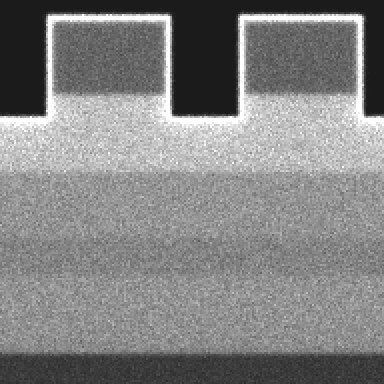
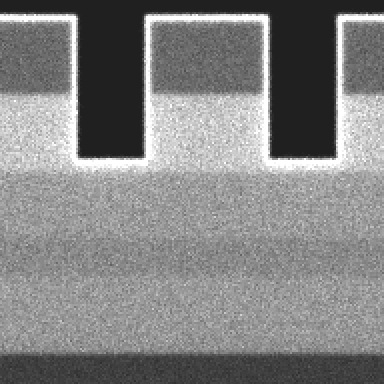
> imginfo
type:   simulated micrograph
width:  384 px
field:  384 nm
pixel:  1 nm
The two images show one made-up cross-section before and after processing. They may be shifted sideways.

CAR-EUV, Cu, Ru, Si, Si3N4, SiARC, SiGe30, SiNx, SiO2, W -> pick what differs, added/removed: W removed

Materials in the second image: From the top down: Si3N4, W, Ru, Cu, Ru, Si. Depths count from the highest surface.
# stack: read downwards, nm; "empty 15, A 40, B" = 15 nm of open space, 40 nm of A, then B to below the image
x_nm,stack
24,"Si3N4 78, W 78, Ru 66, Cu 38, Ru 78, Si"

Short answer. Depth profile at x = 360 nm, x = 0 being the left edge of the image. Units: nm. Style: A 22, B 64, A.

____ Si3N4 78, W 78, Ru 66, Cu 38, Ru 78, Si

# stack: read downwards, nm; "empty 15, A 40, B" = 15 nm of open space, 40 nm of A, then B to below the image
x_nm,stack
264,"Si3N4 78, W 78, Ru 66, Cu 38, Ru 78, Si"